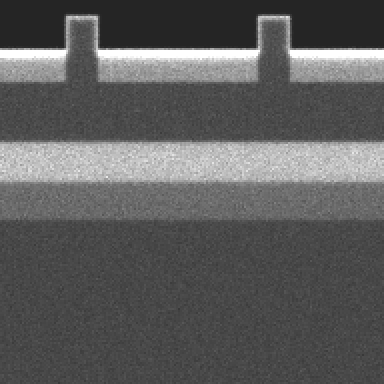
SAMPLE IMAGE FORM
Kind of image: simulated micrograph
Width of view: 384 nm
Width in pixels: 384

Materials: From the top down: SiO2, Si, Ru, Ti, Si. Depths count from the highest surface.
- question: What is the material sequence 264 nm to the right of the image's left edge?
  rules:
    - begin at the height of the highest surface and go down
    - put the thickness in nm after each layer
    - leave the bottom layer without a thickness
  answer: Si 126, Ru 40, Ti 38, Si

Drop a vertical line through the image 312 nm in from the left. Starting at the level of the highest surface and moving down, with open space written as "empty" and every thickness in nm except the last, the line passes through empty 34, SiO2 32, Si 60, Ru 40, Ti 38, Si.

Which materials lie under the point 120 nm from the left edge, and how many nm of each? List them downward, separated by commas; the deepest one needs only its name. empty 34, SiO2 32, Si 60, Ru 40, Ti 38, Si